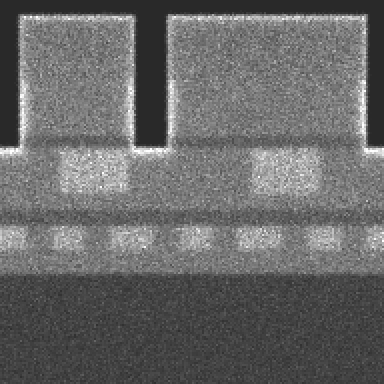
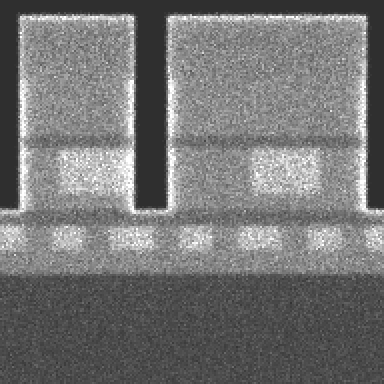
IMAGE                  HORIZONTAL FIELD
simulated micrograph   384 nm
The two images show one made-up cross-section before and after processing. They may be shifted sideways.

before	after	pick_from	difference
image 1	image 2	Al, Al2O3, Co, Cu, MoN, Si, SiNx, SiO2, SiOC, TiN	SiO2 removed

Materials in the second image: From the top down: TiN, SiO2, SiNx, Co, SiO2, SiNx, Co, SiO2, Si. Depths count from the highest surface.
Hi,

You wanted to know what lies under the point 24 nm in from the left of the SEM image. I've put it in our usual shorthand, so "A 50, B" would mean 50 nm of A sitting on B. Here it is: TiN 64, SiO2 56, SiNx 12, SiO2 62, SiNx 16, Co 24, SiO2 24, Si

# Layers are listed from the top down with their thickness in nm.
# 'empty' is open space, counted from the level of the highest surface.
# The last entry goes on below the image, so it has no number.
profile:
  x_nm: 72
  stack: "TiN 64, SiO2 56, SiNx 12, Co 46, SiO2 16, SiNx 16, Co 24, SiO2 24, Si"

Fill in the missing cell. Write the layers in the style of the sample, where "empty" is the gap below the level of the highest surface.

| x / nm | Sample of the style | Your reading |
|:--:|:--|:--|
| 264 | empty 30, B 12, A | TiN 64, SiO2 56, SiNx 12, Co 46, SiO2 16, SiNx 16, Co 24, SiO2 24, Si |